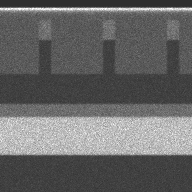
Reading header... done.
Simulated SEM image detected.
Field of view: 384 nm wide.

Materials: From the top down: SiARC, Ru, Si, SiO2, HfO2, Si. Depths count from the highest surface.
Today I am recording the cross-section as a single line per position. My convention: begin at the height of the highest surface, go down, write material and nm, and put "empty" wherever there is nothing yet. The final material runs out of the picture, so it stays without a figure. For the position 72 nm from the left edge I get SiARC 132, Si 60, SiO2 26, HfO2 76, Si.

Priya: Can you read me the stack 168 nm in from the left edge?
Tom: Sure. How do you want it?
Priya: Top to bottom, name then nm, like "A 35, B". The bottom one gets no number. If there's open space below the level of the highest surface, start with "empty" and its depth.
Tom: SiARC 132, Si 60, SiO2 26, HfO2 76, Si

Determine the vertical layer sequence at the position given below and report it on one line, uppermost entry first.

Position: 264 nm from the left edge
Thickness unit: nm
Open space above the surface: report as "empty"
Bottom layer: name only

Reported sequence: SiARC 132, Si 60, SiO2 26, HfO2 76, Si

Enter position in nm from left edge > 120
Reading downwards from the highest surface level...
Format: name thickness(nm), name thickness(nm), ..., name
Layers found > SiARC 132, Si 60, SiO2 26, HfO2 76, Si